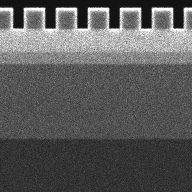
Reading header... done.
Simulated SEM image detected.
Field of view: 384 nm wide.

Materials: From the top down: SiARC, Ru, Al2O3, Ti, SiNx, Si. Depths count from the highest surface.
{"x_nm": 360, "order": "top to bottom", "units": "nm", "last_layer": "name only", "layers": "empty 42, Ru 46, Al2O3 24, Ti 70, SiNx 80, Si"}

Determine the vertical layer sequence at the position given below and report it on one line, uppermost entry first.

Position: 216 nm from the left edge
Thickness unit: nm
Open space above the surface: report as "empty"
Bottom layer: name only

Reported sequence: SiARC 42, Ru 46, Al2O3 24, Ti 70, SiNx 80, Si